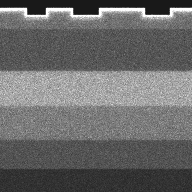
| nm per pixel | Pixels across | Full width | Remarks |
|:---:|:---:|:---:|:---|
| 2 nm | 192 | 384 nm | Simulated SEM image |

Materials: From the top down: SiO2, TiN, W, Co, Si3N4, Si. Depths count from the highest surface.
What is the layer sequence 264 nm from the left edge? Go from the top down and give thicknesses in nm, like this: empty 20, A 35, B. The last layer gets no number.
SiO2 42, TiN 84, W 70, Co 68, Si3N4 58, Si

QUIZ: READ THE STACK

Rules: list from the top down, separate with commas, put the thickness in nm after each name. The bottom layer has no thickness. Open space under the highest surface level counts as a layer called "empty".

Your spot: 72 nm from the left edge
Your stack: empty 14, SiO2 28, TiN 84, W 70, Co 68, Si3N4 58, Si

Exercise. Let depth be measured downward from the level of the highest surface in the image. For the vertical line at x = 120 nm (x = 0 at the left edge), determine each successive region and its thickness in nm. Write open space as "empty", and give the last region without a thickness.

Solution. SiO2 42, TiN 84, W 70, Co 68, Si3N4 58, Si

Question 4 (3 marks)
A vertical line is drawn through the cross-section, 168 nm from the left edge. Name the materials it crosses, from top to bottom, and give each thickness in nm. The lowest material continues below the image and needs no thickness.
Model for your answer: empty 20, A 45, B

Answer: empty 14, SiO2 28, TiN 84, W 70, Co 68, Si3N4 58, Si